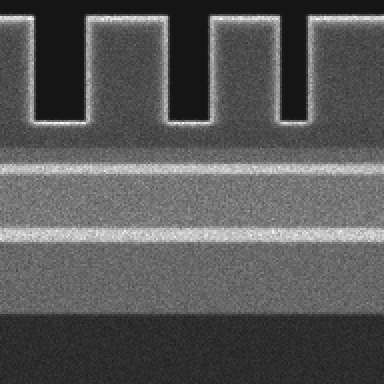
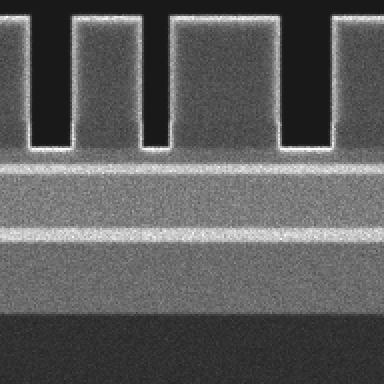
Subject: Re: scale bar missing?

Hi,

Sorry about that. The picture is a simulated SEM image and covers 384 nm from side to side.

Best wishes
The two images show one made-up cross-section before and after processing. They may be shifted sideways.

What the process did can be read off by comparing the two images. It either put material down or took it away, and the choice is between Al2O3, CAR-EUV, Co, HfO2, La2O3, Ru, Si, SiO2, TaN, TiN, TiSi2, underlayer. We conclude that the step removed TiN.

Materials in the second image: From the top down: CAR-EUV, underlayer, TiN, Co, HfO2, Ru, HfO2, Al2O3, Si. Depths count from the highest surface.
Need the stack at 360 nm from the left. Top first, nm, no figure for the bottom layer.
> CAR-EUV 64, underlayer 42, TiN 26, Co 16, HfO2 10, Ru 54, HfO2 14, Al2O3 72, Si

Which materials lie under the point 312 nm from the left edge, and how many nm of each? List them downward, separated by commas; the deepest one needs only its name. empty 132, Co 16, HfO2 10, Ru 54, HfO2 14, Al2O3 72, Si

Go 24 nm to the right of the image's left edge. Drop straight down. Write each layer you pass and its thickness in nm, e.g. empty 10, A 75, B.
CAR-EUV 64, underlayer 42, TiN 26, Co 16, HfO2 10, Ru 54, HfO2 14, Al2O3 72, Si